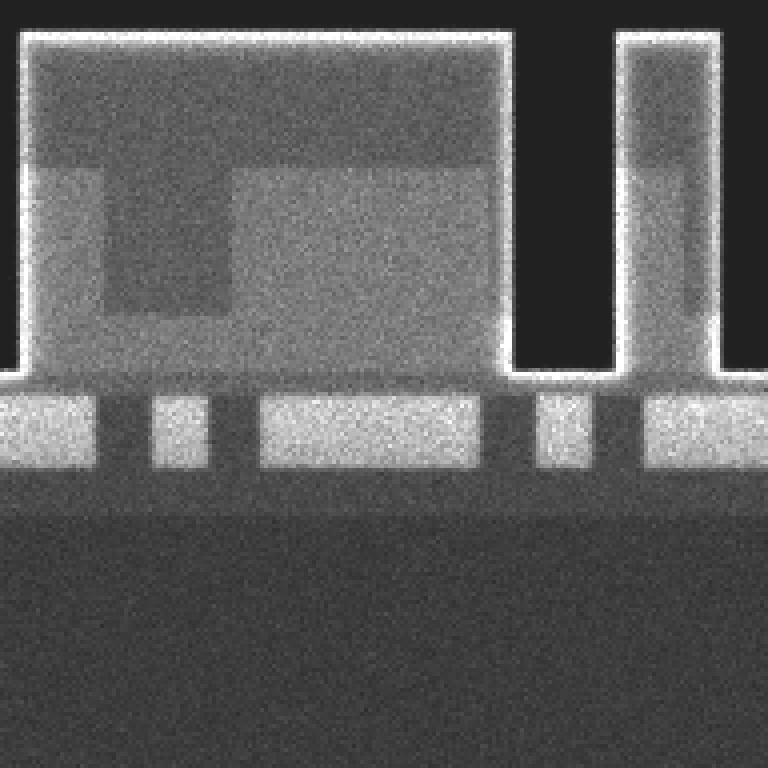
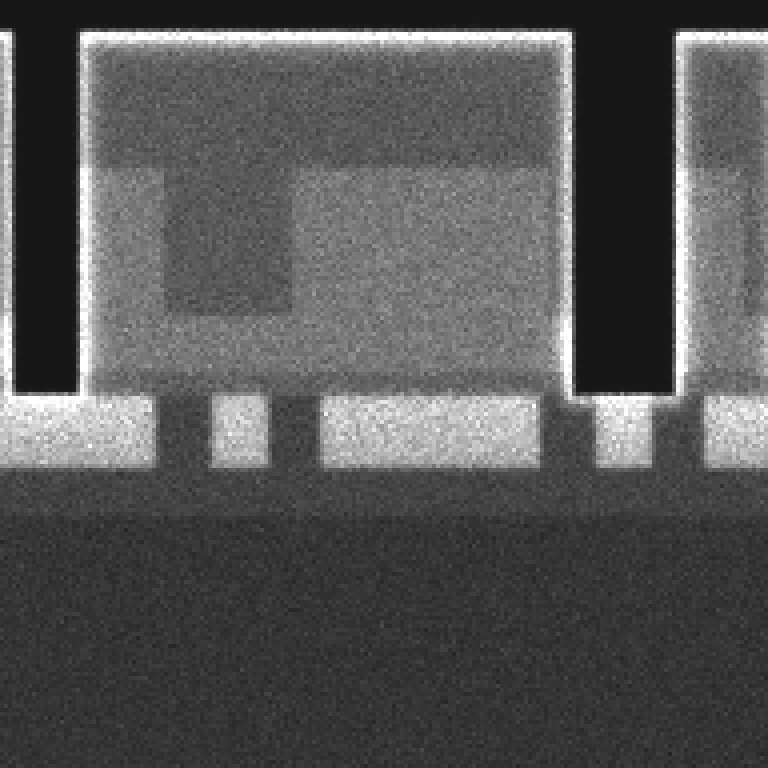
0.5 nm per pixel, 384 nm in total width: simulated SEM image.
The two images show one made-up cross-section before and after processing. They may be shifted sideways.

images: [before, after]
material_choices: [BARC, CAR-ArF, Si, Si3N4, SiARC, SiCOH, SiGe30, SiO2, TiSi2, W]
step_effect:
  removed: Si3N4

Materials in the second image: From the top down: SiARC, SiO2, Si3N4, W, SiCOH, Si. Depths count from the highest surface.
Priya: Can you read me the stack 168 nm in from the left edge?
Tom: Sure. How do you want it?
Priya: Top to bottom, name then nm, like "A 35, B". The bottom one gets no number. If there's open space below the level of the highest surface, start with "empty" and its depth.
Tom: SiARC 68, SiO2 102, Si3N4 12, W 36, SiCOH 24, Si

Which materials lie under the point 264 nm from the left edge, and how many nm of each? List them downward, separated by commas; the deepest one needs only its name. SiARC 68, SiO2 102, Si3N4 12, W 36, SiCOH 24, Si